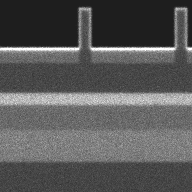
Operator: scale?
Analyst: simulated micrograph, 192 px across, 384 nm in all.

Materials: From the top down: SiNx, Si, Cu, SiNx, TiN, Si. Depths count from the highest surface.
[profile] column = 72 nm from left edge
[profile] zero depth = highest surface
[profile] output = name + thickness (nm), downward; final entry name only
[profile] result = empty 80, SiNx 30, Si 60, Cu 24, SiNx 50, TiN 64, Si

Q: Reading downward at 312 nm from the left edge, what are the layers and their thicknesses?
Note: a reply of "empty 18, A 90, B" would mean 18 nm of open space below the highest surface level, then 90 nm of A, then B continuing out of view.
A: empty 80, SiNx 30, Si 60, Cu 24, SiNx 50, TiN 64, Si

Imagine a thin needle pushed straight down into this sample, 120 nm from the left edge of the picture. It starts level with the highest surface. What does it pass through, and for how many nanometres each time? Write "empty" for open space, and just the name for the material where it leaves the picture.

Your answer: empty 80, SiNx 30, Si 60, Cu 24, SiNx 50, TiN 64, Si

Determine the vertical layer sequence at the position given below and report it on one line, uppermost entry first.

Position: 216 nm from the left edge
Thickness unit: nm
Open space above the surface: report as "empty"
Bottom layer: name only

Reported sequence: empty 80, SiNx 30, Si 60, Cu 24, SiNx 50, TiN 64, Si